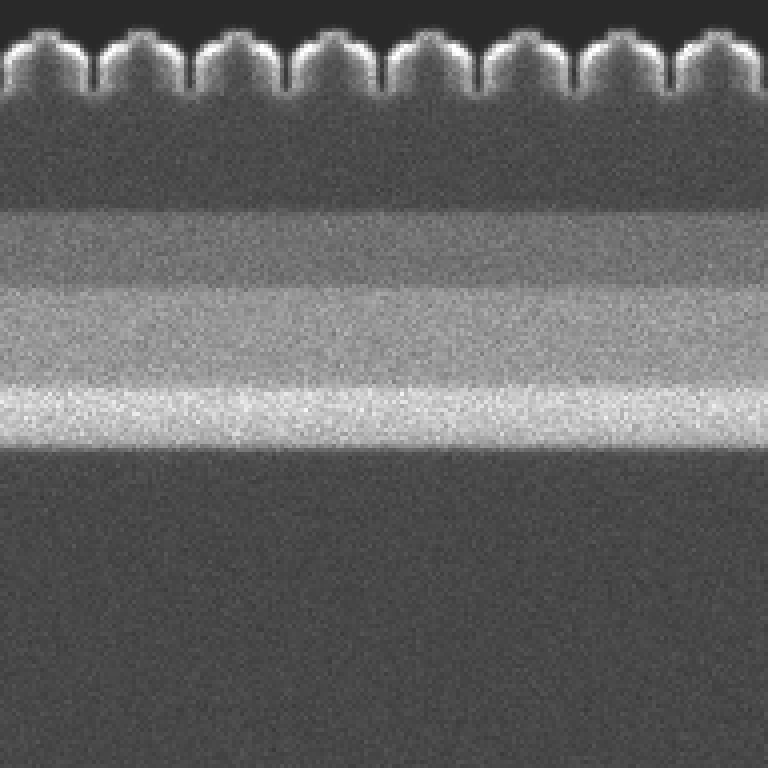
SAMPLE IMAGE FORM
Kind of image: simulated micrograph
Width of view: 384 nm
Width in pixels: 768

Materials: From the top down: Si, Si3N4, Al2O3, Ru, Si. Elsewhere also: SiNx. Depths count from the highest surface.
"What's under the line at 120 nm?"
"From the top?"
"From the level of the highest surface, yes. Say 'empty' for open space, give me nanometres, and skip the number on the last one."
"Si 90, Si3N4 38, Al2O3 50, Ru 30, Si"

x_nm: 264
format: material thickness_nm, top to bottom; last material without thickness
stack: Si 90, Si3N4 38, Al2O3 50, Ru 30, Si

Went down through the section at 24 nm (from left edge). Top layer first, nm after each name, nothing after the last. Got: Si 90, Si3N4 38, Al2O3 50, Ru 30, Si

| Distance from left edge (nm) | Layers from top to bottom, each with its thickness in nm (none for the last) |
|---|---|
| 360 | Si 90, Si3N4 38, Al2O3 50, Ru 30, Si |